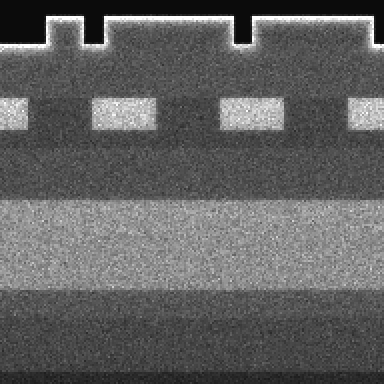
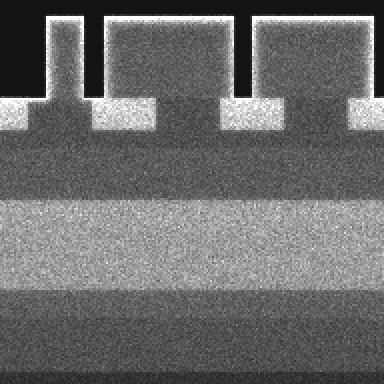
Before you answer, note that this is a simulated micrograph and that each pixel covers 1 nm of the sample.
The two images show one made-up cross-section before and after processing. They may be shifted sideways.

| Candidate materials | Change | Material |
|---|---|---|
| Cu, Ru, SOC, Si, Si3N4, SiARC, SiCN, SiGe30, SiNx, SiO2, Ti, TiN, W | removed | SOC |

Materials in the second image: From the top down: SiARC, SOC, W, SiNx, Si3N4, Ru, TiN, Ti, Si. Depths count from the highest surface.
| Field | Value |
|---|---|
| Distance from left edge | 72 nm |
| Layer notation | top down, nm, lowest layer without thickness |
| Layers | SiARC 28, SOC 54, SiNx 50, Si3N4 52, Ru 90, TiN 28, Ti 54, Si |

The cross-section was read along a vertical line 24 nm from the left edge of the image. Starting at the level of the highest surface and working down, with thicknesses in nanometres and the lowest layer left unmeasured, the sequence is empty 82, W 32, SiNx 18, Si3N4 52, Ru 90, TiN 28, Ti 54, Si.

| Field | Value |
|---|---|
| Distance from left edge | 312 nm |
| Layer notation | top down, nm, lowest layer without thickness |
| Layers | SiARC 28, SOC 54, SiNx 50, Si3N4 52, Ru 90, TiN 28, Ti 54, Si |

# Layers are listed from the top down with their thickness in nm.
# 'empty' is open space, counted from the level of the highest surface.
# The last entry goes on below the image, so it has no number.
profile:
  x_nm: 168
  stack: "SiARC 28, SOC 54, SiNx 50, Si3N4 52, Ru 90, TiN 28, Ti 54, Si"